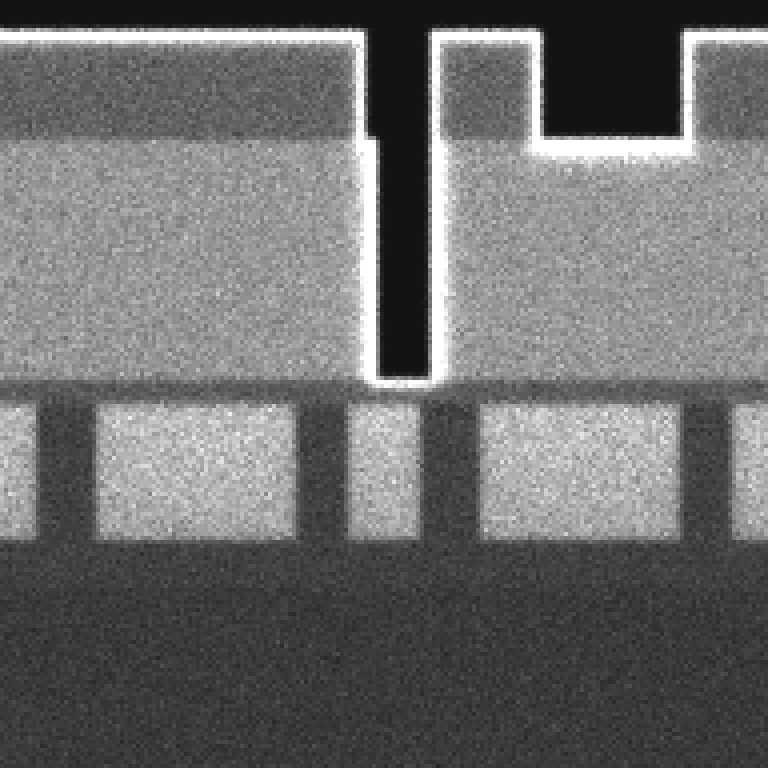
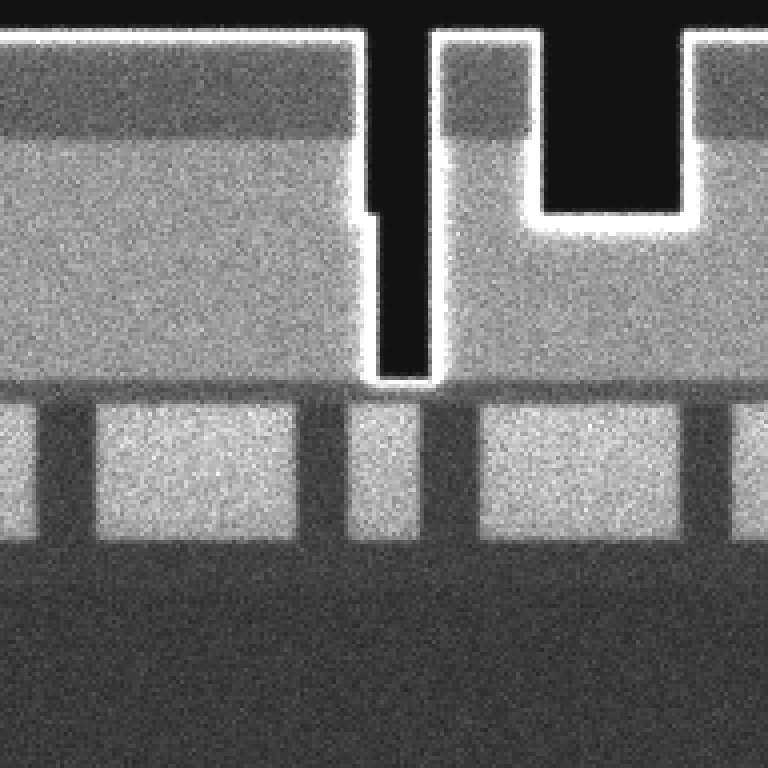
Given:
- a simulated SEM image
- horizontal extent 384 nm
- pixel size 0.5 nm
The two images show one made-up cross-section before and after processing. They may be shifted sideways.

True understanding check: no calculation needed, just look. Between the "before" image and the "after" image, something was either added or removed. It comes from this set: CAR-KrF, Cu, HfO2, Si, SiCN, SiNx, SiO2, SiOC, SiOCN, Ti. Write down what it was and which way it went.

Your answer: SiO2 (removed)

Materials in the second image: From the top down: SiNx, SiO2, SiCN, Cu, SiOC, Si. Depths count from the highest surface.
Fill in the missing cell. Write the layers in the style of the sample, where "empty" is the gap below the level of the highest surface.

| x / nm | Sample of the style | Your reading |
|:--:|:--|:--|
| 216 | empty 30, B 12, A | SiNx 54, SiO2 120, SiCN 12, SiOC 92, Si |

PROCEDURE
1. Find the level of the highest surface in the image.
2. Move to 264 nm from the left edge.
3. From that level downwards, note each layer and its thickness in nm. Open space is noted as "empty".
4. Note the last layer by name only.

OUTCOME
SiNx 54, SiO2 120, SiCN 12, Cu 68, SiOC 24, Si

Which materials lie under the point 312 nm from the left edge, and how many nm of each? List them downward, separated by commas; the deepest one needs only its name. empty 92, SiO2 82, SiCN 12, Cu 68, SiOC 24, Si